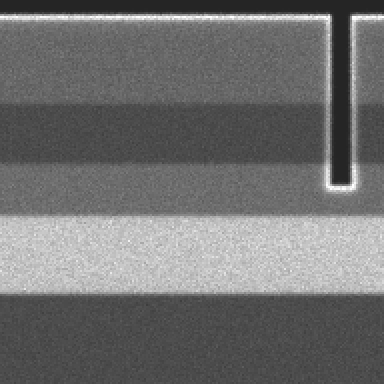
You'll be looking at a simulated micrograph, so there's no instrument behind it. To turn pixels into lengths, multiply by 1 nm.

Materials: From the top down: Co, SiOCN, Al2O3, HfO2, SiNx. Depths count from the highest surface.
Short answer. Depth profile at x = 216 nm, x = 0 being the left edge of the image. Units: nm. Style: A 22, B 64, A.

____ Co 88, SiOCN 60, Al2O3 52, HfO2 78, SiNx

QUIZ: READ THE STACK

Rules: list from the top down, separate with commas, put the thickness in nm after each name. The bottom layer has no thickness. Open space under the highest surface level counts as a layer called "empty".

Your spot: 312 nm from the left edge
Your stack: Co 88, SiOCN 60, Al2O3 52, HfO2 78, SiNx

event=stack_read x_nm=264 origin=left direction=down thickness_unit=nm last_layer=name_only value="Co 88, SiOCN 60, Al2O3 52, HfO2 78, SiNx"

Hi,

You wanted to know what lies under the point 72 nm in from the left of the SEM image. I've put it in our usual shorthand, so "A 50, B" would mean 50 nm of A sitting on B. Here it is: Co 88, SiOCN 60, Al2O3 52, HfO2 78, SiNx